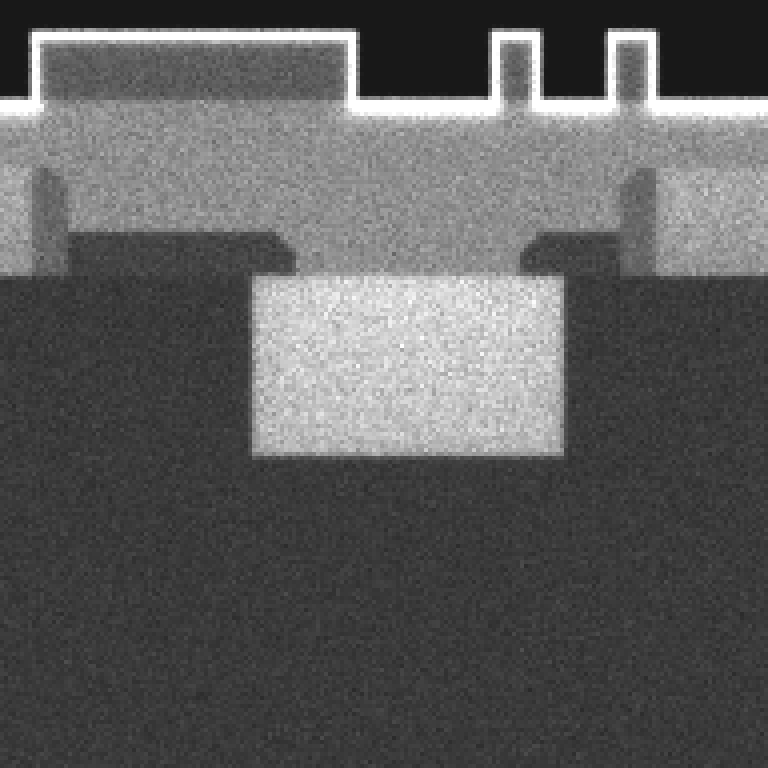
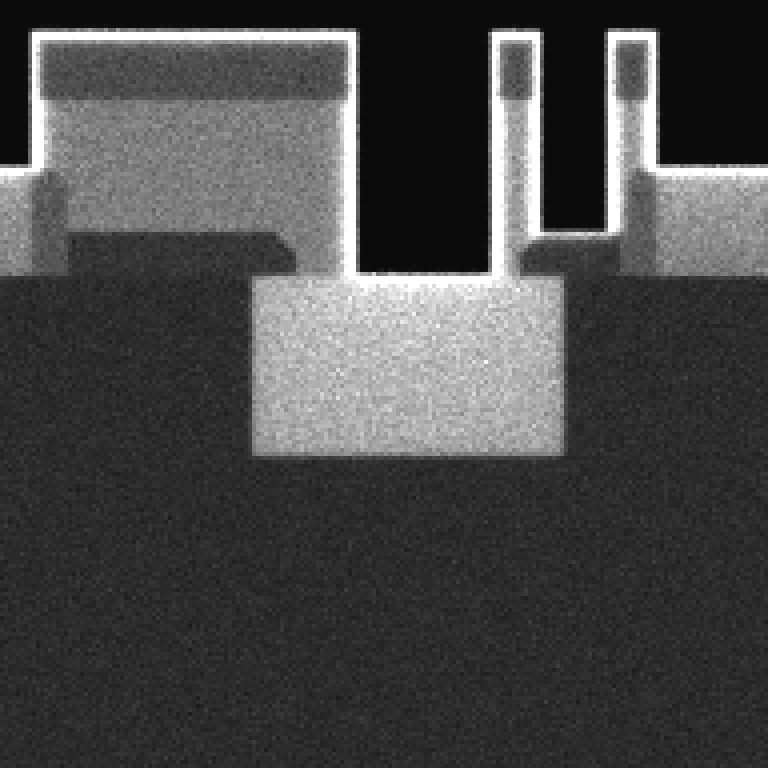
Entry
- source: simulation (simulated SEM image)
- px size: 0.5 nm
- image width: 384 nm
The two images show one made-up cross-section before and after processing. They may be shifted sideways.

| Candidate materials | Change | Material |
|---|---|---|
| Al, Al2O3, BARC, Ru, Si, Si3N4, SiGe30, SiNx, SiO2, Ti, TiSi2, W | removed | SiO2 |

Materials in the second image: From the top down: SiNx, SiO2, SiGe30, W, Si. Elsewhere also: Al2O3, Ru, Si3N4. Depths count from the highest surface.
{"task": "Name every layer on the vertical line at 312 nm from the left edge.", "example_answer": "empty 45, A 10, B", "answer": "SiNx 34, SiO2 40, Si3N4 48, Si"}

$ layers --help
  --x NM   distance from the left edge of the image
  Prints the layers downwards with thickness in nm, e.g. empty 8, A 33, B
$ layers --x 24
SiNx 34, SiO2 34, Si3N4 54, Si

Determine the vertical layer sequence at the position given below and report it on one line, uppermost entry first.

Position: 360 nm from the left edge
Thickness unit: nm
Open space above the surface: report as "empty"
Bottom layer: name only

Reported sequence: empty 68, Ru 44, Al2O3 10, Si